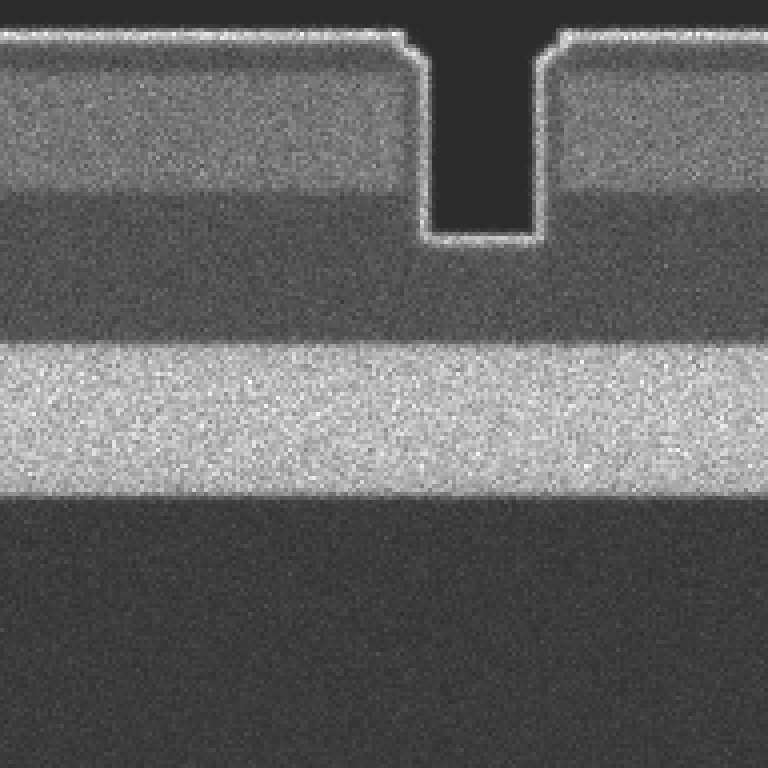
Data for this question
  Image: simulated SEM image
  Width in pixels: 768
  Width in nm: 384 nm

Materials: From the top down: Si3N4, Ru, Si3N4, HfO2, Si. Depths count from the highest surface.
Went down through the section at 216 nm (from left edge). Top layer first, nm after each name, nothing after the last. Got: empty 102, Si3N4 54, HfO2 76, Si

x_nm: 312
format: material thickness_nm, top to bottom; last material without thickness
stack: Si3N4 20, Ru 60, Si3N4 76, HfO2 76, Si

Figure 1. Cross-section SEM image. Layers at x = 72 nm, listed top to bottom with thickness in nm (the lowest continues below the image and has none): Si3N4 20, Ru 60, Si3N4 76, HfO2 76, Si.